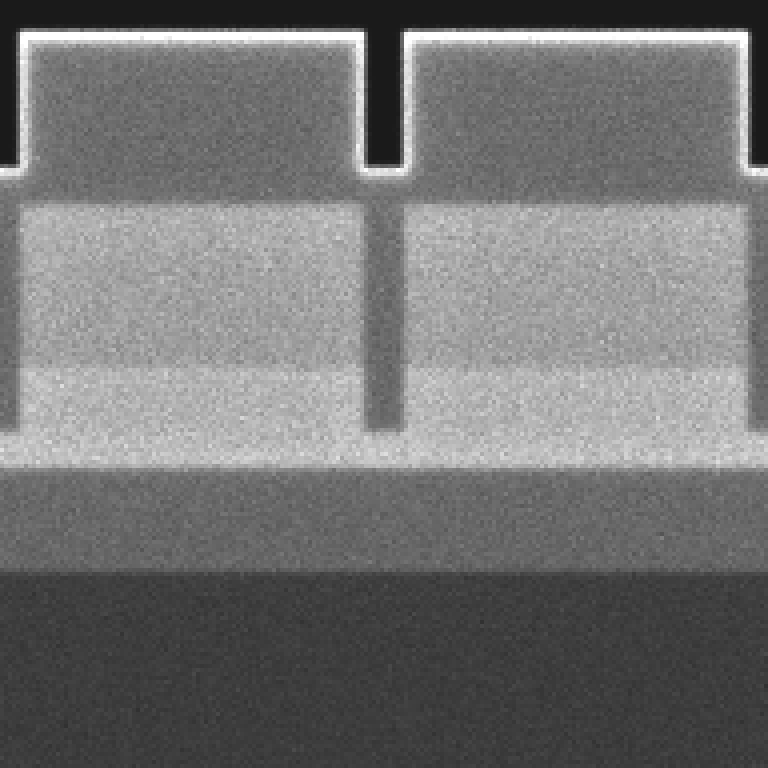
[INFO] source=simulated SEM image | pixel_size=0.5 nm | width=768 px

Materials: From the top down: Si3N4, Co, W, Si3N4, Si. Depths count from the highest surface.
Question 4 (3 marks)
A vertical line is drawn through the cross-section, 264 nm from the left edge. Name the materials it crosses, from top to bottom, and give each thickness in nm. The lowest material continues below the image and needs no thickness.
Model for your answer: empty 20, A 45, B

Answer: Si3N4 86, Co 82, W 50, Si3N4 52, Si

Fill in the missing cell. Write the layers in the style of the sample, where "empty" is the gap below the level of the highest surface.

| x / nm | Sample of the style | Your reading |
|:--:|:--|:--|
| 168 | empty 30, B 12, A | Si3N4 86, Co 82, W 50, Si3N4 52, Si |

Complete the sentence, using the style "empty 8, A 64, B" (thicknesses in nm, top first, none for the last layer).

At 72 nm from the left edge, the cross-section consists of Si3N4 86, Co 82, W 50, Si3N4 52, Si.